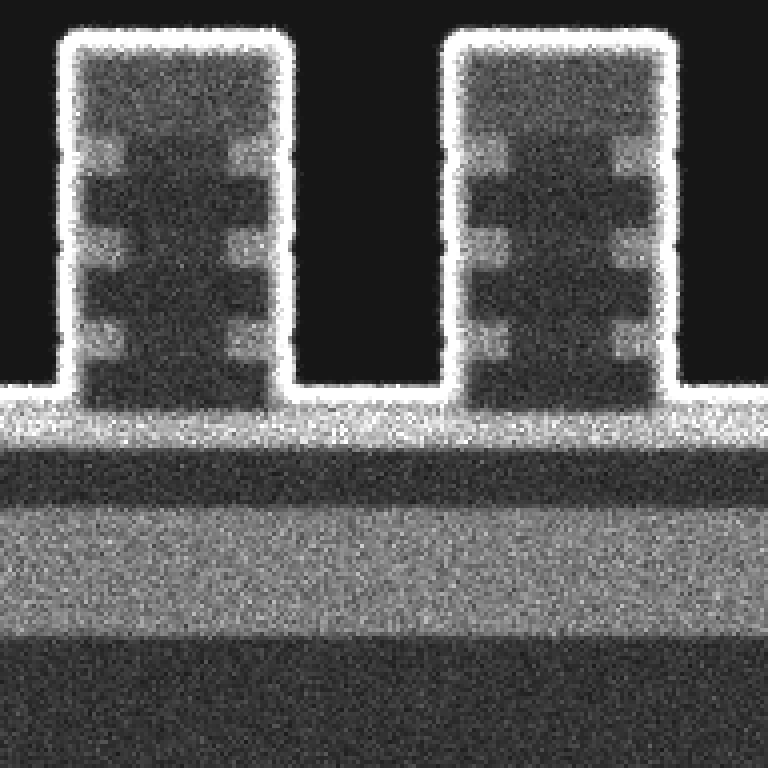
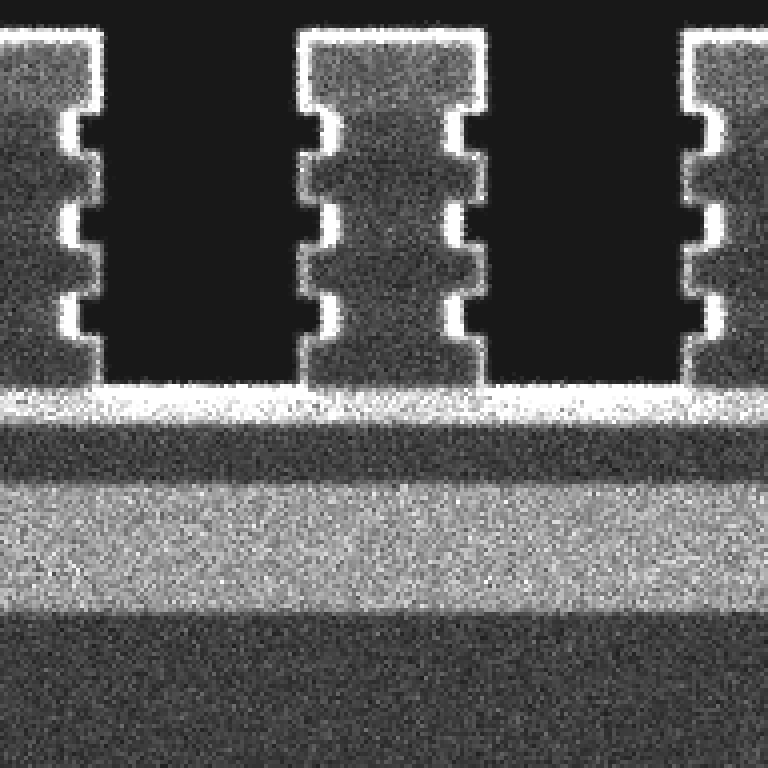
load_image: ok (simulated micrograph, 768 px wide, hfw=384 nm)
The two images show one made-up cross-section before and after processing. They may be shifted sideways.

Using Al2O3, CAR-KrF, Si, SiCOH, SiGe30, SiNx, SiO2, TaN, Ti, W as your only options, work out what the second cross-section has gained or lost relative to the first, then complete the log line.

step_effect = removed Al2O3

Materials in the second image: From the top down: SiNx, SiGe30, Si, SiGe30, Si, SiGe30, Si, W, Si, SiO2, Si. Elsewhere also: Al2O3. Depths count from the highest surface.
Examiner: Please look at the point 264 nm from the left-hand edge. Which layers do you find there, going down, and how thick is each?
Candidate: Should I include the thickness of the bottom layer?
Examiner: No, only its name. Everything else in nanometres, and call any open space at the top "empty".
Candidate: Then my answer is empty 178, W 18, Si 30, SiO2 64, Si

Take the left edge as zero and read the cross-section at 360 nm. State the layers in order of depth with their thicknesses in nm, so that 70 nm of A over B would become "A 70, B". SiNx 40, Al2O3 20, Si 26, Al2O3 20, Si 26, Al2O3 20, Si 26, W 18, Si 30, SiO2 64, Si